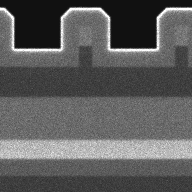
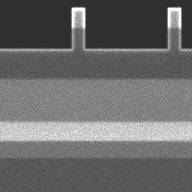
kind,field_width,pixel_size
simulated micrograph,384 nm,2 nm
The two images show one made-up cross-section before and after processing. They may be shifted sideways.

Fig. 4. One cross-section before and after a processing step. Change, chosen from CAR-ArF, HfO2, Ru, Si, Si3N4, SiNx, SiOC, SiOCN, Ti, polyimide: SiNx removed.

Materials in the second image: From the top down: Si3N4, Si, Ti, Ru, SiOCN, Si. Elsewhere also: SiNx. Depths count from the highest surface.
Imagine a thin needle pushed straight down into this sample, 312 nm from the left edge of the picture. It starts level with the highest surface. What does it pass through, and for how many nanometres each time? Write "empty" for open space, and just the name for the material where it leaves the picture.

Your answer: empty 82, Si 60, Ti 86, Ru 38, SiOCN 34, Si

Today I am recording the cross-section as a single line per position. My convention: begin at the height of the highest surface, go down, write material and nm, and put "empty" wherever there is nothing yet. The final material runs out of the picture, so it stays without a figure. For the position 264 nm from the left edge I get empty 82, Si 60, Ti 86, Ru 38, SiOCN 34, Si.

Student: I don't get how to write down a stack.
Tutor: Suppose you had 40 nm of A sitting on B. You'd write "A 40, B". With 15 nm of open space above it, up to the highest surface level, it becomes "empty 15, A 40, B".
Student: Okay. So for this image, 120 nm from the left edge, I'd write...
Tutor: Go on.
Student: empty 82, Si 60, Ti 86, Ru 38, SiOCN 34, Si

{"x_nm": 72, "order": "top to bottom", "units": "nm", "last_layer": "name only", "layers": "empty 82, Si 60, Ti 86, Ru 38, SiOCN 34, Si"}